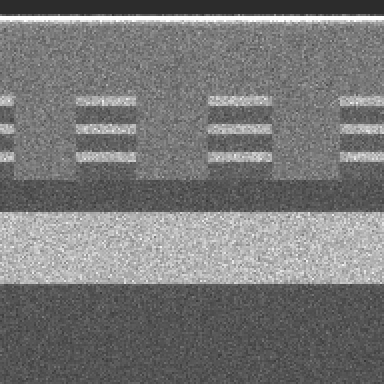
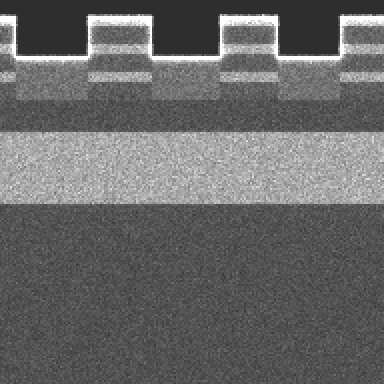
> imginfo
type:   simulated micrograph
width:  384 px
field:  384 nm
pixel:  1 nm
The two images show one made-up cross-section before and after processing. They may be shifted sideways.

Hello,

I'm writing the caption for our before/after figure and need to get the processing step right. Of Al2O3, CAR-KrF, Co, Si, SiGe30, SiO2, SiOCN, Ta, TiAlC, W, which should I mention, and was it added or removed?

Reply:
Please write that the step removed SiOCN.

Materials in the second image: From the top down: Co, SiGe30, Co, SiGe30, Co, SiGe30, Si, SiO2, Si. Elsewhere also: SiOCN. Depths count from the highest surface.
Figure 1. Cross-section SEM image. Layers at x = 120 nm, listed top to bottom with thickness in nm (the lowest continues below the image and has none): Co 10, SiGe30 18, Co 10, SiGe30 18, Co 10, SiGe30 18, Si 32, SiO2 72, Si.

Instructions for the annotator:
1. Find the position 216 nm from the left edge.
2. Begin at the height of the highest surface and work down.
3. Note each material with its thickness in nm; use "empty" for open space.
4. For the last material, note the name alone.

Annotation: empty 40, SiOCN 44, Si 32, SiO2 72, Si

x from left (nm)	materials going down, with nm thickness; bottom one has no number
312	empty 40, SiOCN 44, Si 32, SiO2 72, Si